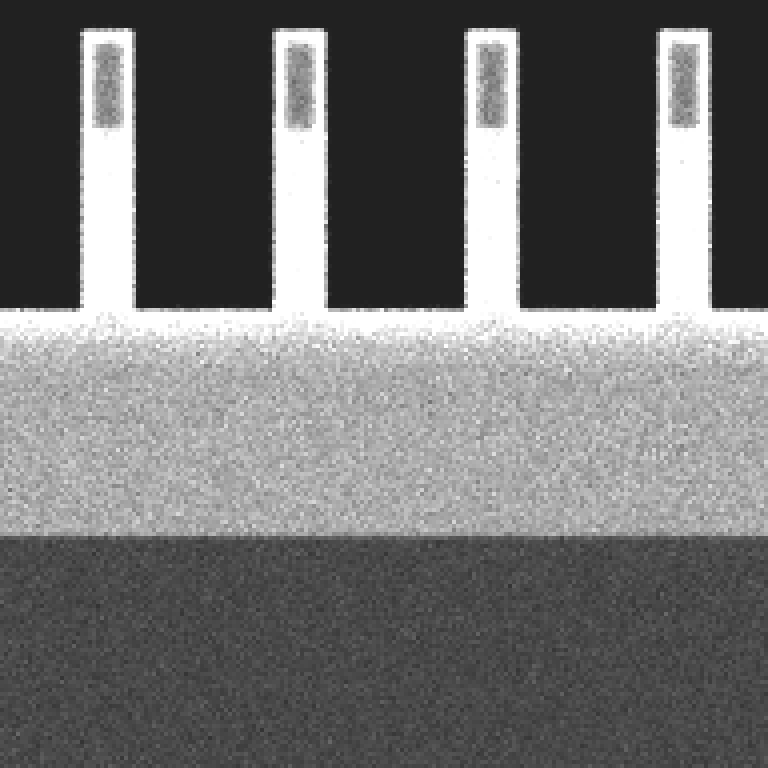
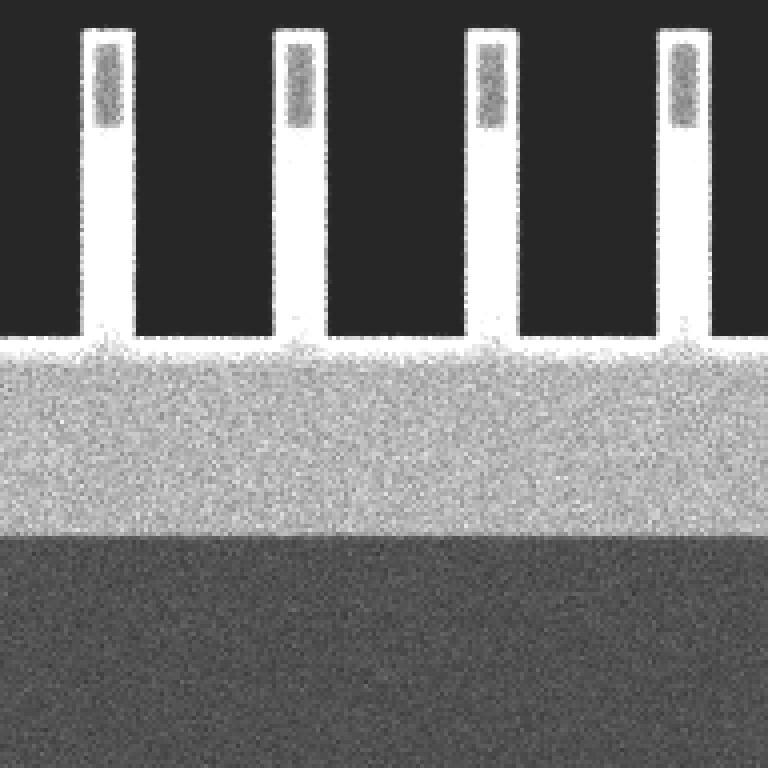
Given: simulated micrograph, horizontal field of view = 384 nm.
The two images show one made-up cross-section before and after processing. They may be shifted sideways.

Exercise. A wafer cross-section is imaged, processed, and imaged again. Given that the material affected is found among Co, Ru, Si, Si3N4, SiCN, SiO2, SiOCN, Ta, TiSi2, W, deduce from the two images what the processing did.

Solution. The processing removed Ru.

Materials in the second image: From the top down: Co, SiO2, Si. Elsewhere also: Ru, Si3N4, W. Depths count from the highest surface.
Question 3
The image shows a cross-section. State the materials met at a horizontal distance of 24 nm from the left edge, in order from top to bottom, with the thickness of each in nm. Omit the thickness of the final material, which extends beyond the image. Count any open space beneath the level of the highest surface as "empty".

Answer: empty 154, Co 12, SiO2 86, Si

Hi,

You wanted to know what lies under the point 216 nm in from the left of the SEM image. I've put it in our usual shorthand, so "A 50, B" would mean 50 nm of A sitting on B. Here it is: empty 154, Co 12, SiO2 86, Si